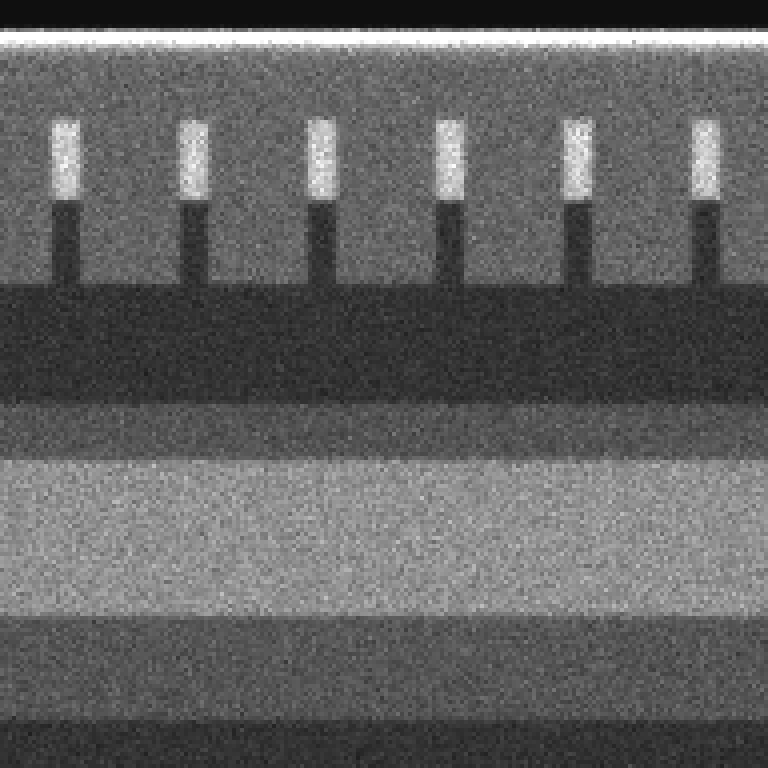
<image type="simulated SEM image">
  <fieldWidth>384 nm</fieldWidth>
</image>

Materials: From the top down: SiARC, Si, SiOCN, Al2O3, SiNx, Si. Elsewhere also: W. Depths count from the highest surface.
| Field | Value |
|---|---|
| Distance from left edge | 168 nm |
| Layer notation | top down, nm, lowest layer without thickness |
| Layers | SiARC 126, Si 60, SiOCN 28, Al2O3 78, SiNx 52, Si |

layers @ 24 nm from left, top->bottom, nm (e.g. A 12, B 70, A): SiARC 126, Si 60, SiOCN 28, Al2O3 78, SiNx 52, Si